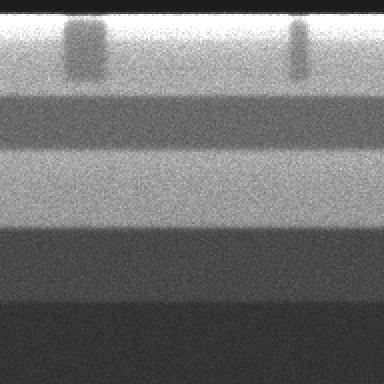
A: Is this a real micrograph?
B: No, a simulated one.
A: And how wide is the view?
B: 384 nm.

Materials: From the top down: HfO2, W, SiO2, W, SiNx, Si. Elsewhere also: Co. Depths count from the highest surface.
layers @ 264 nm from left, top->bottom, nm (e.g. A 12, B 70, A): HfO2 24, W 56, SiO2 54, W 78, SiNx 74, Si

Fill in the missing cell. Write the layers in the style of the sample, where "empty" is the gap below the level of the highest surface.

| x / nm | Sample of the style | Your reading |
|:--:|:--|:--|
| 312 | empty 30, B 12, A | HfO2 24, W 56, SiO2 54, W 78, SiNx 74, Si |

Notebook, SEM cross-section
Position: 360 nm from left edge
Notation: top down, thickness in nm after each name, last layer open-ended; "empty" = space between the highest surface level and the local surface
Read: HfO2 24, W 56, SiO2 54, W 78, SiNx 74, Si